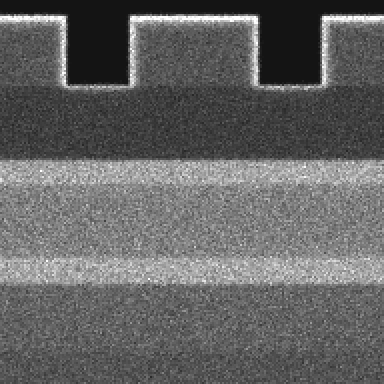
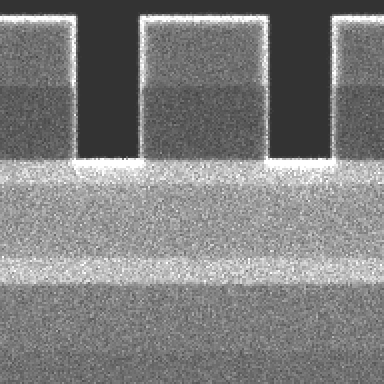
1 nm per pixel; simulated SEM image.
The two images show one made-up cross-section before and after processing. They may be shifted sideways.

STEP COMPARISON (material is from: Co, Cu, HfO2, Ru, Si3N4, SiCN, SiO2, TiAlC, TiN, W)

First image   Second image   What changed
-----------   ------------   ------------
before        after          TiN, removed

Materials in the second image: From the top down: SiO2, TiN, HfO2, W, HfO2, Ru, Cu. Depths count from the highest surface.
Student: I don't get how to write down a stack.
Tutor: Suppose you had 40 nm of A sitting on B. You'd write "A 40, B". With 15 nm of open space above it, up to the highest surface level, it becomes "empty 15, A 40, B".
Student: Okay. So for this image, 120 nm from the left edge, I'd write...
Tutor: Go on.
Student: empty 144, HfO2 24, W 74, HfO2 26, Ru 68, Cu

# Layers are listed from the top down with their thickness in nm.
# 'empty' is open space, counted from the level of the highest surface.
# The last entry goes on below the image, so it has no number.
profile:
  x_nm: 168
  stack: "SiO2 70, TiN 74, HfO2 24, W 74, HfO2 26, Ru 68, Cu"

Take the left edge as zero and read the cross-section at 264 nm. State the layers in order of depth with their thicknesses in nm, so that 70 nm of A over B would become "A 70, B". SiO2 70, TiN 74, HfO2 24, W 74, HfO2 26, Ru 68, Cu